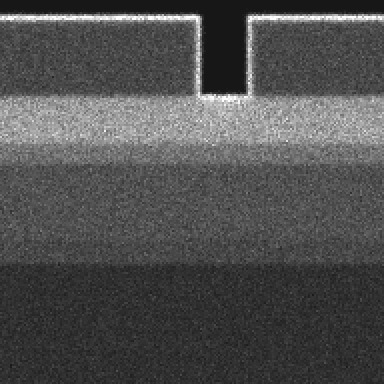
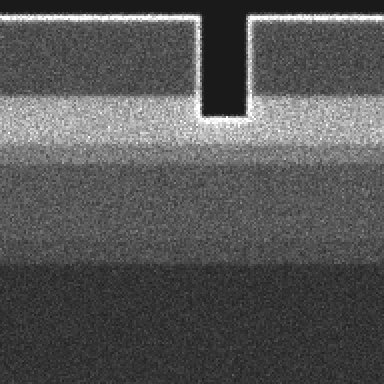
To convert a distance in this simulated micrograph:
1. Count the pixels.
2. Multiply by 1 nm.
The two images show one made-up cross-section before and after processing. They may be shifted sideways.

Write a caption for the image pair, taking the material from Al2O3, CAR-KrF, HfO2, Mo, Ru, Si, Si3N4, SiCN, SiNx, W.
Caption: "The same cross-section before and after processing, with W removed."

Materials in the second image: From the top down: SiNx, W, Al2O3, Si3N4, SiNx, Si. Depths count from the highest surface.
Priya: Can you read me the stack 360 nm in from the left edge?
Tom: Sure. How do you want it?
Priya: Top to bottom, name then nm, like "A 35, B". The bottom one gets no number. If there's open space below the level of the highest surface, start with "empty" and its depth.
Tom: SiNx 80, W 48, Al2O3 20, Si3N4 76, SiNx 24, Si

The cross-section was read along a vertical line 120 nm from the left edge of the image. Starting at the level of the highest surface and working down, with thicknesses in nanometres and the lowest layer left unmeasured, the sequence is SiNx 80, W 48, Al2O3 20, Si3N4 76, SiNx 24, Si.